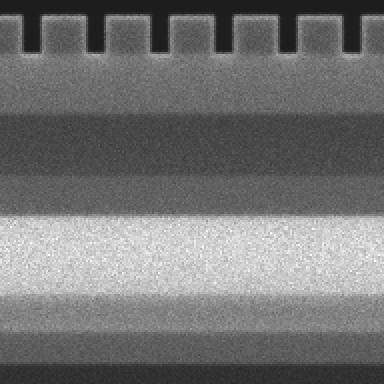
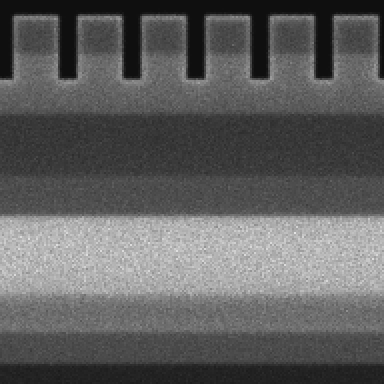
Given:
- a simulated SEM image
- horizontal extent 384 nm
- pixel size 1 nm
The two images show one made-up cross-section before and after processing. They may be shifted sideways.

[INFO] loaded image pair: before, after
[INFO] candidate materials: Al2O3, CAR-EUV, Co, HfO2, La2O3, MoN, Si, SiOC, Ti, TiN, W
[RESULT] removed Co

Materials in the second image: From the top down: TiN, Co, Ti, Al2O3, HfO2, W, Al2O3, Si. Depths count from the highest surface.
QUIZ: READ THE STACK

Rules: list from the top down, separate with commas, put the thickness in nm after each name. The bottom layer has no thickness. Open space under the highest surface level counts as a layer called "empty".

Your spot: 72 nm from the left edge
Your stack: empty 64, Co 34, Ti 62, Al2O3 40, HfO2 78, W 38, Al2O3 32, Si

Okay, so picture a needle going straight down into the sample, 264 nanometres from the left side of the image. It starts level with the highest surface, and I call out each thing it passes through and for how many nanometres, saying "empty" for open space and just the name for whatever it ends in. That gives empty 64, Co 34, Ti 62, Al2O3 40, HfO2 78, W 38, Al2O3 32, Si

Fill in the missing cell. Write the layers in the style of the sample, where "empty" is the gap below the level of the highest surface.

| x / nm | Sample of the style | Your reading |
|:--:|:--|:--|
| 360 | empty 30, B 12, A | TiN 38, Co 60, Ti 62, Al2O3 40, HfO2 78, W 38, Al2O3 32, Si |